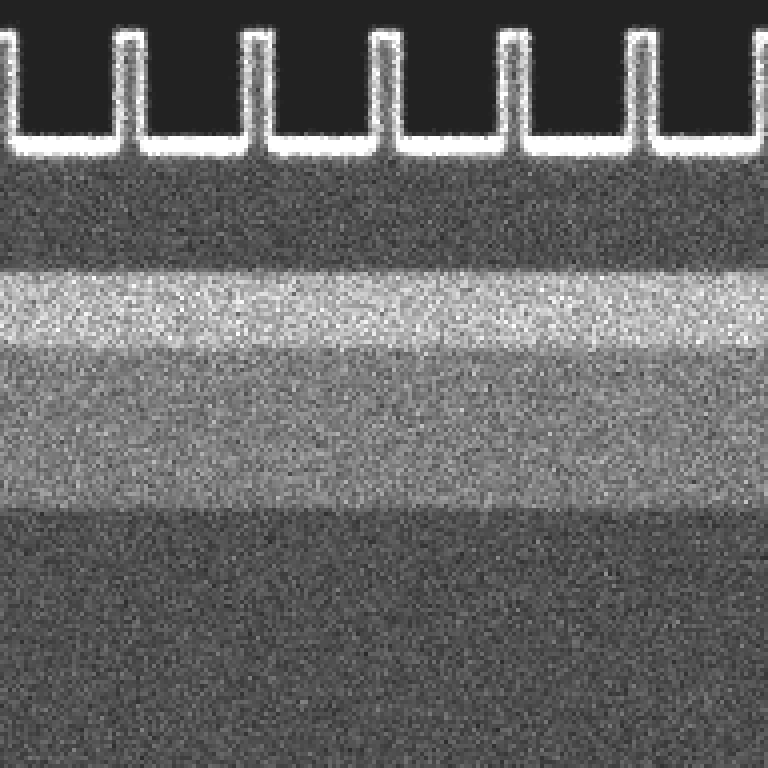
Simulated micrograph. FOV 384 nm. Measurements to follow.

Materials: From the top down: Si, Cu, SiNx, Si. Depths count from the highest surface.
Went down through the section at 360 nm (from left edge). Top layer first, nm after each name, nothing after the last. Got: empty 54, Si 66, Cu 38, SiNx 80, Si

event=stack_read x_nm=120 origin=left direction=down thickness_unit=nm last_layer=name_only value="empty 54, Si 66, Cu 38, SiNx 80, Si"